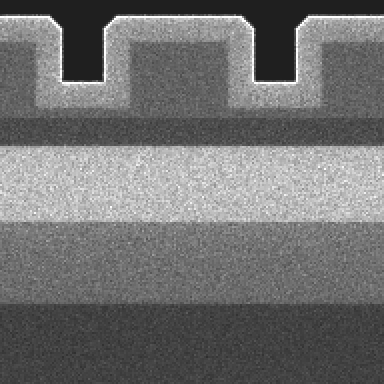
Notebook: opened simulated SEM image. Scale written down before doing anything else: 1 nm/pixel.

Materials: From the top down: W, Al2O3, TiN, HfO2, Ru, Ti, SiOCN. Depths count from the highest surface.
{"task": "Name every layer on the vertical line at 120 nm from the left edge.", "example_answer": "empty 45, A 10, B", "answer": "W 92, Al2O3 10, TiN 28, HfO2 76, Ru 82, Ti 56, SiOCN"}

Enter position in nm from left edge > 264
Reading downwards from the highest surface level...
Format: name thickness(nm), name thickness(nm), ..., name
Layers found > empty 66, W 26, Al2O3 10, TiN 28, HfO2 76, Ru 82, Ti 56, SiOCN